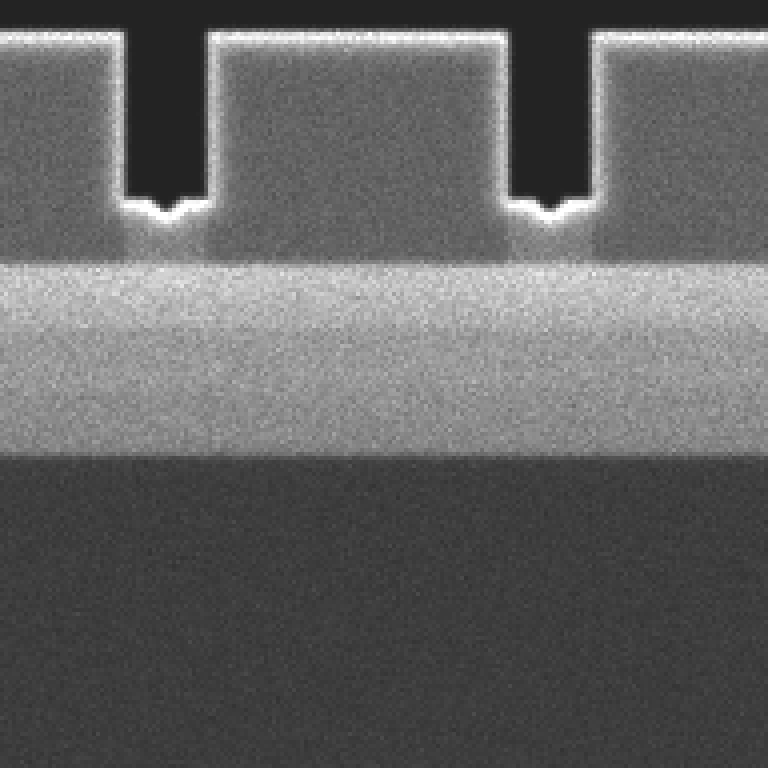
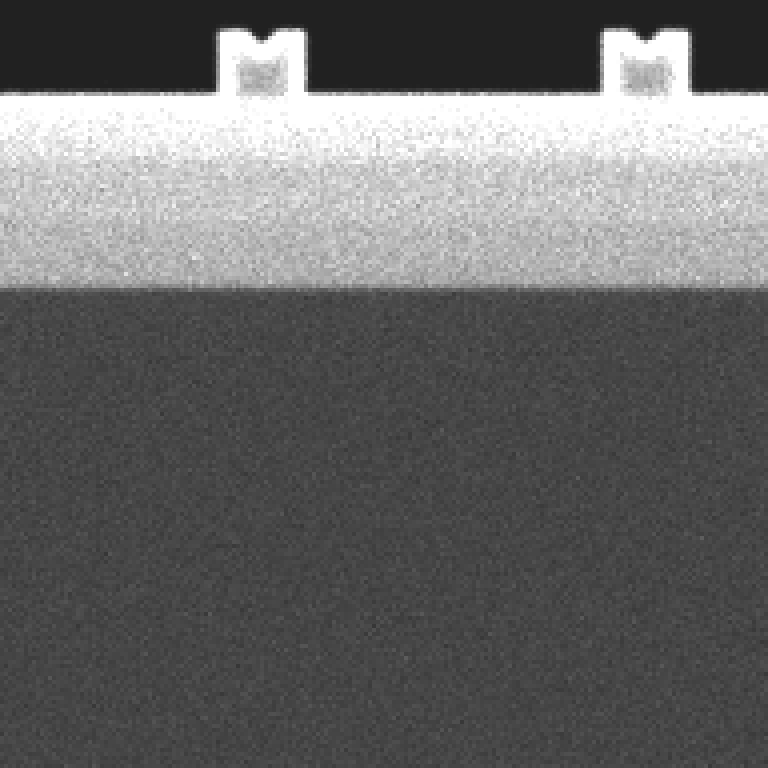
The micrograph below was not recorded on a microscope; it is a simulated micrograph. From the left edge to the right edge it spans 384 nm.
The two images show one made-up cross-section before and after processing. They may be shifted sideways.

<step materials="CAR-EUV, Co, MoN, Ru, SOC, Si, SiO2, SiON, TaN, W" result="removed SOC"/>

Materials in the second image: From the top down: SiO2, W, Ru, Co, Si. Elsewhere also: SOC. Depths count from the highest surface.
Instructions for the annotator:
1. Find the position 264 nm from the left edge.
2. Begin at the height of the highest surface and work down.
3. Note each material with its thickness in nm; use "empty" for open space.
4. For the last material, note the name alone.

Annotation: empty 32, W 32, Ru 30, Co 34, Si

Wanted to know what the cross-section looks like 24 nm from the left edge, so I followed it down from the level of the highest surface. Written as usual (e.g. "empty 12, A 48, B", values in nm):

empty 32, W 32, Ru 30, Co 34, Si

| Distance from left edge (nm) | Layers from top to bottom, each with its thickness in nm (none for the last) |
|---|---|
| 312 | SiO2 32, W 32, Ru 30, Co 34, Si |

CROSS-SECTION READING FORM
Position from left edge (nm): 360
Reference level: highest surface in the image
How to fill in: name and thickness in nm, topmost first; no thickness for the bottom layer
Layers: empty 32, W 32, Ru 30, Co 34, Si